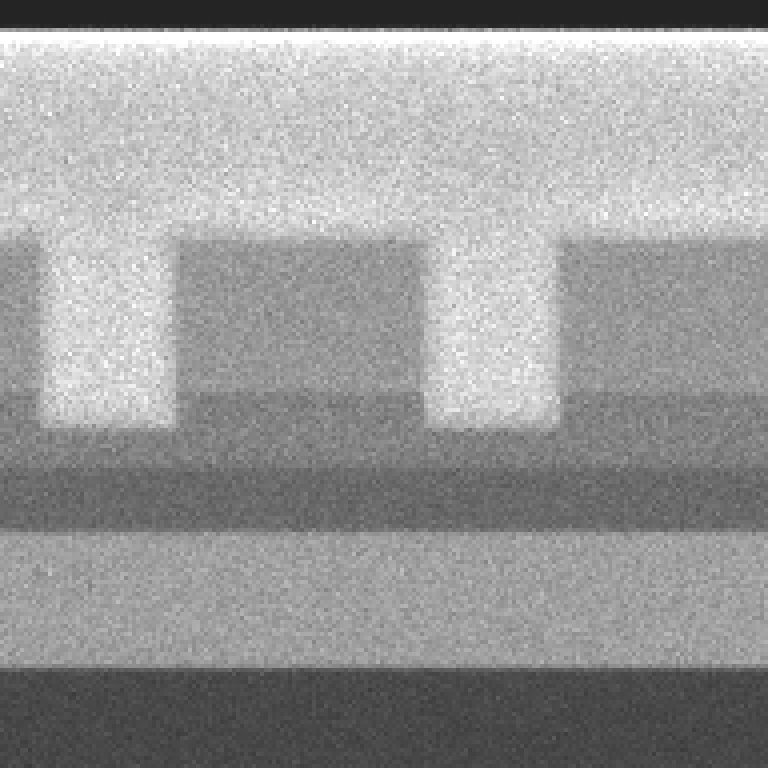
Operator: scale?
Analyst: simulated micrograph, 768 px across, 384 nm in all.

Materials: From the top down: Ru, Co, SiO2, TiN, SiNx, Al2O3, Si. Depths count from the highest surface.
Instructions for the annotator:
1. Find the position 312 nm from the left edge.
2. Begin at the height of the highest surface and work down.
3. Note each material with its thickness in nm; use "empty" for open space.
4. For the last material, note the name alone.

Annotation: Ru 96, Co 8, SiO2 76, TiN 38, SiNx 32, Al2O3 68, Si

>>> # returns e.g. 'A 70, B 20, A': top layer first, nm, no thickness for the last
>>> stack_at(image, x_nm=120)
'Ru 96, Co 8, SiO2 76, TiN 38, SiNx 32, Al2O3 68, Si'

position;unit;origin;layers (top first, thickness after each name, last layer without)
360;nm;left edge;Ru 96, Co 8, SiO2 76, TiN 38, SiNx 32, Al2O3 68, Si